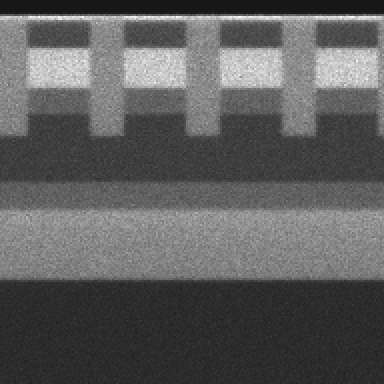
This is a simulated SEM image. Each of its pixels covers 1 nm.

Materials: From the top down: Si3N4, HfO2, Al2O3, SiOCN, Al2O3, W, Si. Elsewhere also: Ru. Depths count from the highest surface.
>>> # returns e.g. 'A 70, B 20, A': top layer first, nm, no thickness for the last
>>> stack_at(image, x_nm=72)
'Si3N4 32, HfO2 40, Al2O3 26, SiOCN 68, Al2O3 28, W 70, Si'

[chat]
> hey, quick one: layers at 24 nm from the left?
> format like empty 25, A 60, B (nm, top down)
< Ru 120, SiOCN 46, Al2O3 28, W 70, Si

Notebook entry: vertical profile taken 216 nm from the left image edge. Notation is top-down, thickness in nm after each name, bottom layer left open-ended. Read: Ru 120, SiOCN 46, Al2O3 28, W 70, Si